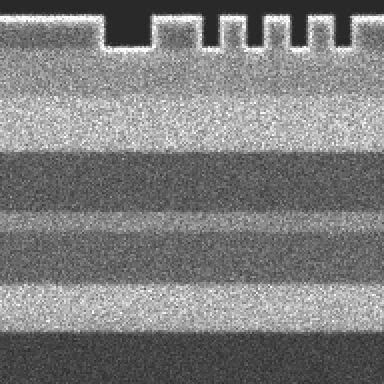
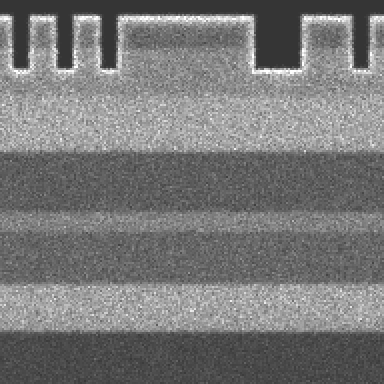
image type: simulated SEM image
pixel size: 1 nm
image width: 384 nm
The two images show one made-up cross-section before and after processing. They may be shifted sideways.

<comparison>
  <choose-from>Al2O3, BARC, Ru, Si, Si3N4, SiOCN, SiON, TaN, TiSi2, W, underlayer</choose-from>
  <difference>Ru removed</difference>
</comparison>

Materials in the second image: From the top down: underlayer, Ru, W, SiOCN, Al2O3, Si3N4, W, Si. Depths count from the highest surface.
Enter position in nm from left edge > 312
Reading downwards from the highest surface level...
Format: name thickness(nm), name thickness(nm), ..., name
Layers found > underlayer 32, Ru 48, W 56, SiOCN 60, Al2O3 20, Si3N4 52, W 48, Si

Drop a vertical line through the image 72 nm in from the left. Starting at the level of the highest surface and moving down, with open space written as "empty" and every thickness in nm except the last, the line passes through empty 54, Ru 26, W 56, SiOCN 60, Al2O3 20, Si3N4 52, W 48, Si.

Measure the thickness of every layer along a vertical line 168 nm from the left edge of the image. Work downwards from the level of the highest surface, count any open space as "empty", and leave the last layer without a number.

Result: underlayer 32, Ru 48, W 56, SiOCN 60, Al2O3 20, Si3N4 52, W 48, Si